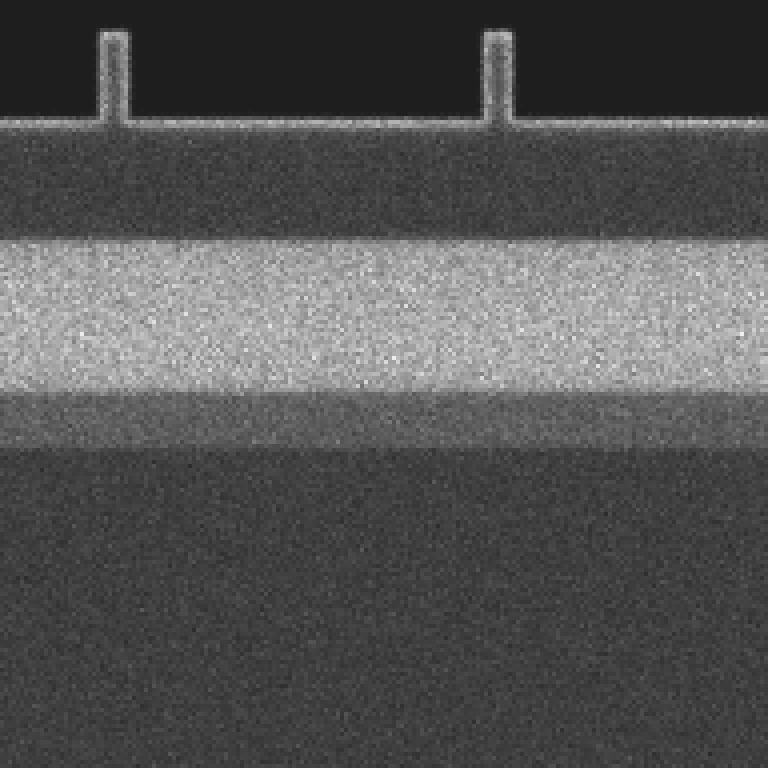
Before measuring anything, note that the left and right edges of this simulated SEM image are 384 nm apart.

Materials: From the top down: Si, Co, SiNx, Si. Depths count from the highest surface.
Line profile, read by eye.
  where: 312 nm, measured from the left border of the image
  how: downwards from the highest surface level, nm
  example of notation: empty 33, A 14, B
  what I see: empty 44, Si 60, Co 76, SiNx 28, Si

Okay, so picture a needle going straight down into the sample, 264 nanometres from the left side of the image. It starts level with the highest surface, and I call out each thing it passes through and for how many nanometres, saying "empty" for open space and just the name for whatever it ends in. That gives empty 44, Si 60, Co 76, SiNx 28, Si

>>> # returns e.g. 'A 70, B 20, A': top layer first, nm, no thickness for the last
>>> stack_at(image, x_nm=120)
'empty 44, Si 60, Co 76, SiNx 28, Si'